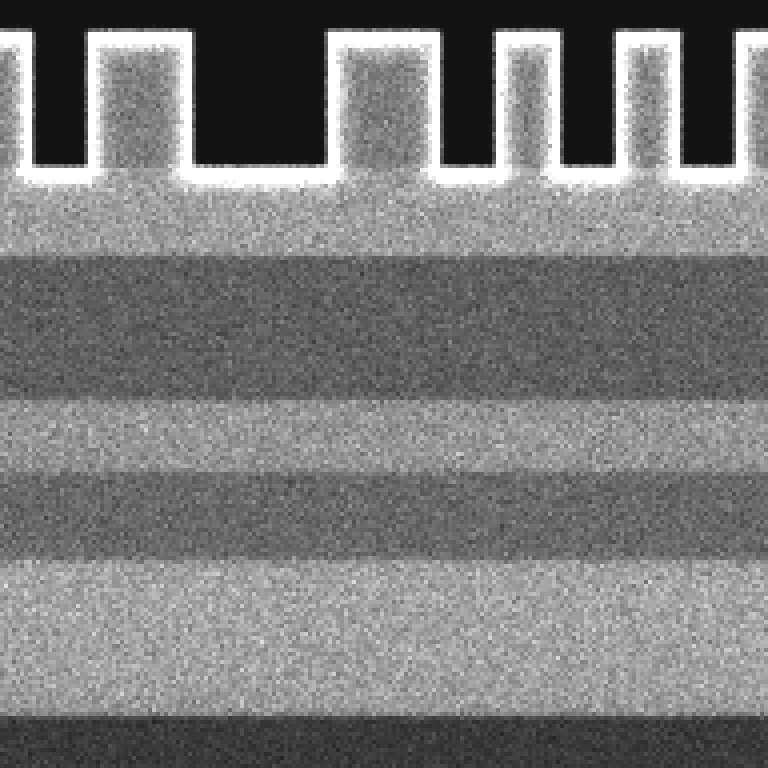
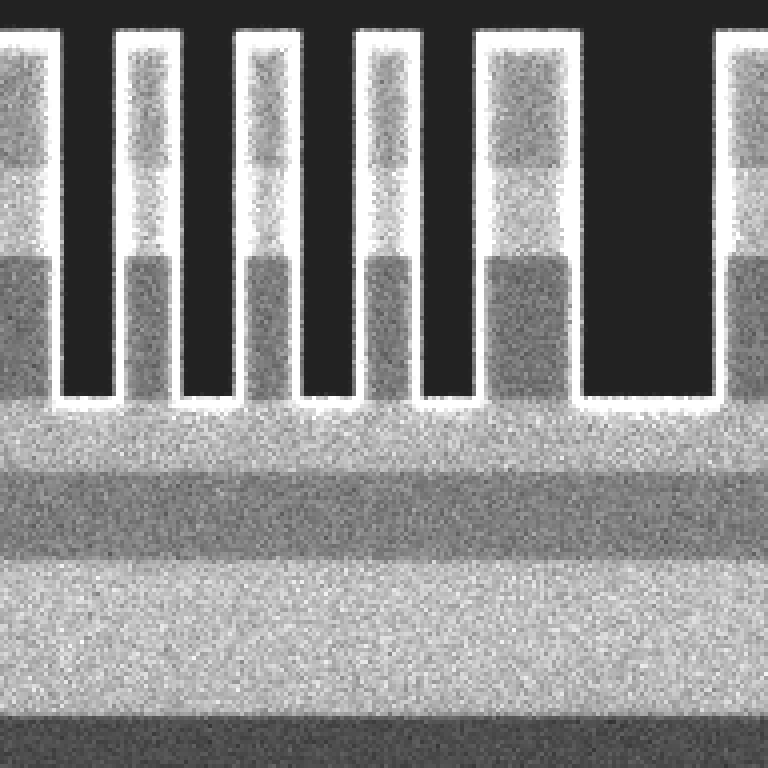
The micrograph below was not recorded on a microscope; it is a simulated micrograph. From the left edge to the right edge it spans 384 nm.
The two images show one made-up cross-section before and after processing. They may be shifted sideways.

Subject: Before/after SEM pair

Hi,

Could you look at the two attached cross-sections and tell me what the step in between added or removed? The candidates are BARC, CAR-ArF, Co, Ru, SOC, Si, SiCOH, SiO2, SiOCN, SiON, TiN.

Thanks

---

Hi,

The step removed SiO2 and SiOCN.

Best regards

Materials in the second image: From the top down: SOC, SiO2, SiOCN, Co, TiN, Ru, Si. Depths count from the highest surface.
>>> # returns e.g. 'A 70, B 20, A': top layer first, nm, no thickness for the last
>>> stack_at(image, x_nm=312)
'empty 184, Co 36, TiN 44, Ru 78, Si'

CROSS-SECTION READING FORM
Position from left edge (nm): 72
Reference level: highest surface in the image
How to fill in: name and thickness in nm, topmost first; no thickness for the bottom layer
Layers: SOC 68, SiO2 44, SiOCN 72, Co 36, TiN 44, Ru 78, Si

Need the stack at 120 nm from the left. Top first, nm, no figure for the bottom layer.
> SOC 68, SiO2 44, SiOCN 72, Co 36, TiN 44, Ru 78, Si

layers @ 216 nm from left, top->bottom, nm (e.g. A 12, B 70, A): empty 184, Co 36, TiN 44, Ru 78, Si